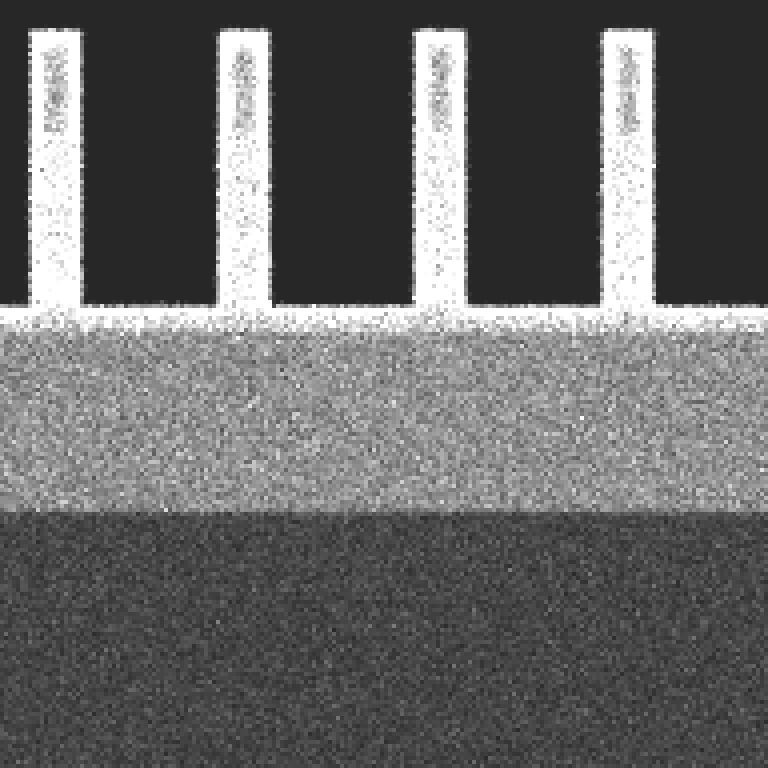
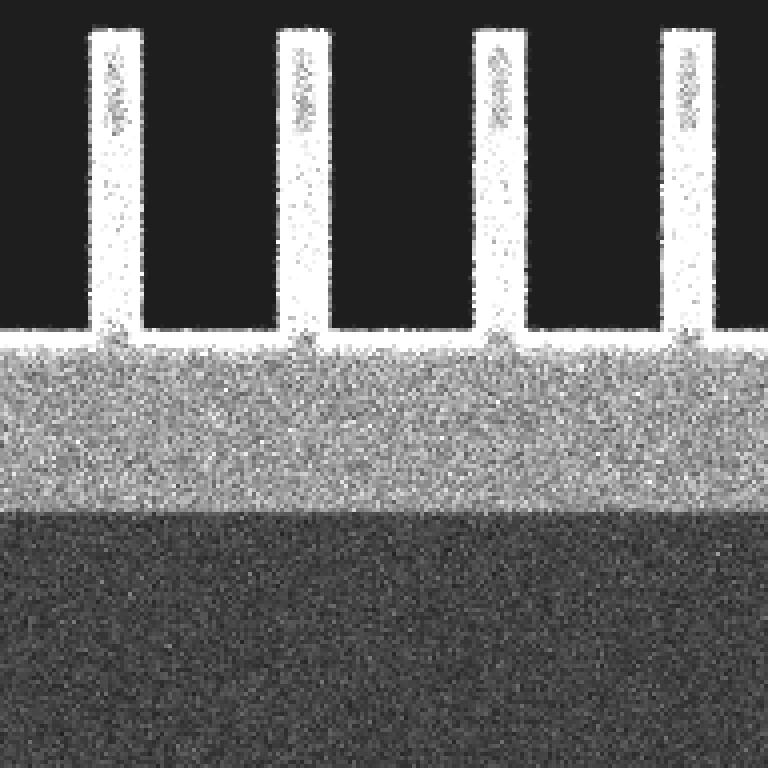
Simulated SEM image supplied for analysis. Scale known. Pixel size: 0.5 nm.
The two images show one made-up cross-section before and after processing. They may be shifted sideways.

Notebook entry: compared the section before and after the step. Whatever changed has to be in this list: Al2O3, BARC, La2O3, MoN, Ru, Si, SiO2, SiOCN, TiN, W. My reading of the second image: Ru removed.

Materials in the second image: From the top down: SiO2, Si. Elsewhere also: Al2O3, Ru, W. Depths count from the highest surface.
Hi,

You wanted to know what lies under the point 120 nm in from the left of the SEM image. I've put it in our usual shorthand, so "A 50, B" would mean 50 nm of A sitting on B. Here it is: empty 150, SiO2 90, Si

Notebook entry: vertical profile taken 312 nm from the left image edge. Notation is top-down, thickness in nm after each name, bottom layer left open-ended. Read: empty 150, SiO2 90, Si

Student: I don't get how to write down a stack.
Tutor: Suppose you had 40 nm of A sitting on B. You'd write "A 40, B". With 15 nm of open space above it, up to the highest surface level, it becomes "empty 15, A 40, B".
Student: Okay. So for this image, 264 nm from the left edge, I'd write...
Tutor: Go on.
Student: empty 150, SiO2 90, Si